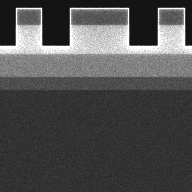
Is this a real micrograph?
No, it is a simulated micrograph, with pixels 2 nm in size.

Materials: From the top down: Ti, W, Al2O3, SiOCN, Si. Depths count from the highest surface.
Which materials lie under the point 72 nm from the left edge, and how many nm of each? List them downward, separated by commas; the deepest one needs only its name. Ti 34, W 58, Al2O3 46, SiOCN 26, Si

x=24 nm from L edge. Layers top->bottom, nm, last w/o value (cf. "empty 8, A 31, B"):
empty 76, W 16, Al2O3 46, SiOCN 26, Si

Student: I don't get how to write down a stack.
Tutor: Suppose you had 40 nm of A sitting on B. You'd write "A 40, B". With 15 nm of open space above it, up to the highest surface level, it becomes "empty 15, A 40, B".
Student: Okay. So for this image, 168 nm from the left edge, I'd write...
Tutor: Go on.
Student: Ti 34, W 58, Al2O3 46, SiOCN 26, Si